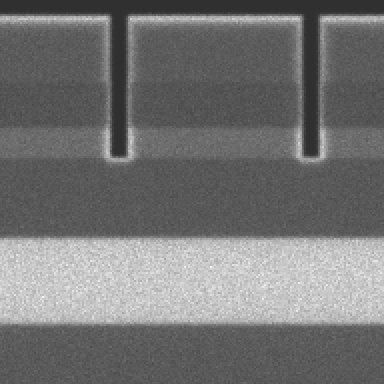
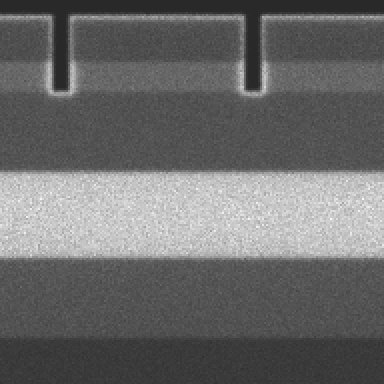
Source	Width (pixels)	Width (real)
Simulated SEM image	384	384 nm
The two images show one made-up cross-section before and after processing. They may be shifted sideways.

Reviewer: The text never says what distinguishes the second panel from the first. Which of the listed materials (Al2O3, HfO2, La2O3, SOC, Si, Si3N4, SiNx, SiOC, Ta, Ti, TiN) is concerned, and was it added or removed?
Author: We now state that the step removed SOC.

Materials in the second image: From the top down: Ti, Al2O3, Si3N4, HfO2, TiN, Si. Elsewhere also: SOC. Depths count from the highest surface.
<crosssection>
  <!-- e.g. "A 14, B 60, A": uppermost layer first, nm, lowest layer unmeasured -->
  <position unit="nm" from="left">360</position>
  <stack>Ti 46, Al2O3 30, Si3N4 80, HfO2 86, TiN 80, Si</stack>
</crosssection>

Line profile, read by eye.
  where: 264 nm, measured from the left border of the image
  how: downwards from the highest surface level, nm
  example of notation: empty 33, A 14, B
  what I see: Ti 46, Al2O3 30, Si3N4 80, HfO2 86, TiN 80, Si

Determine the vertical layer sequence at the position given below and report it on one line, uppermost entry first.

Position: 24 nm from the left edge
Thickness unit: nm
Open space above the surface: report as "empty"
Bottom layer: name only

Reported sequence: Ti 46, Al2O3 30, Si3N4 80, HfO2 86, TiN 80, Si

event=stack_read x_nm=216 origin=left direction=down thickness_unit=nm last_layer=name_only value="Ti 46, Al2O3 30, Si3N4 80, HfO2 86, TiN 80, Si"